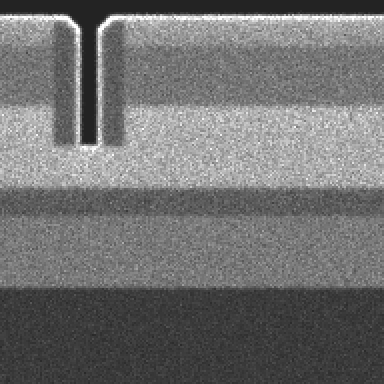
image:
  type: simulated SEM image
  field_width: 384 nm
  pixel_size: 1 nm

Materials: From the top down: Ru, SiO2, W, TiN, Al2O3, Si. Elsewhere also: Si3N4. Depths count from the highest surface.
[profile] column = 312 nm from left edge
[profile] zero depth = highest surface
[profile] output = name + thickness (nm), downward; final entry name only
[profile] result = Ru 30, SiO2 60, W 82, TiN 28, Al2O3 72, Si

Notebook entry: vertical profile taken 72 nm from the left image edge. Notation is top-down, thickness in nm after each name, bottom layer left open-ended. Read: empty 6, Si3N4 124, W 42, TiN 28, Al2O3 72, Si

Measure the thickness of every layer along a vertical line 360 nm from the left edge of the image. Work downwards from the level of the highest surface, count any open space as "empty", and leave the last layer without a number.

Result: Ru 30, SiO2 60, W 82, TiN 28, Al2O3 72, Si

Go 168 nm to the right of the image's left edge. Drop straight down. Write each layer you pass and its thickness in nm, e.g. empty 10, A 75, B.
Ru 30, SiO2 60, W 82, TiN 28, Al2O3 72, Si